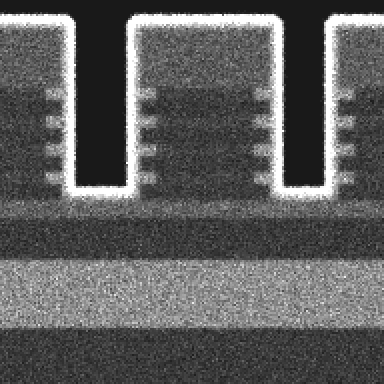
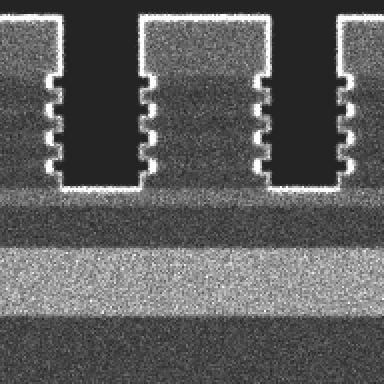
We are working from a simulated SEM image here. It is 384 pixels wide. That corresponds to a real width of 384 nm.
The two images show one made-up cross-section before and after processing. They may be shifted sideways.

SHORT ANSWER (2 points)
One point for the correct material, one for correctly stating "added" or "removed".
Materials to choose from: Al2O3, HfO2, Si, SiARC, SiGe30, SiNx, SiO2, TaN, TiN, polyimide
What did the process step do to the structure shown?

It removed Al2O3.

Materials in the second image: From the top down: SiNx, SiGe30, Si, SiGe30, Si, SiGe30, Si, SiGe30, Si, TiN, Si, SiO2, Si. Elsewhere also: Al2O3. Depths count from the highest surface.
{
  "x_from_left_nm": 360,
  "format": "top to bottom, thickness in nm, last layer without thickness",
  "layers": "SiNx 60, SiGe30 12, Si 16, SiGe30 12, Si 16, SiGe30 12, Si 16, SiGe30 12, Si 16, TiN 18, Si 42, SiO2 68, Si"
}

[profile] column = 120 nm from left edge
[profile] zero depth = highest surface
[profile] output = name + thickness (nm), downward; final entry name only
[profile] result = empty 172, TiN 18, Si 42, SiO2 68, Si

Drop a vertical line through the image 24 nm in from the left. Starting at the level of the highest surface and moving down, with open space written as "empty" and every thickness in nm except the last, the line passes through SiNx 60, SiGe30 12, Si 16, SiGe30 12, Si 16, SiGe30 12, Si 16, SiGe30 12, Si 16, TiN 18, Si 42, SiO2 68, Si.